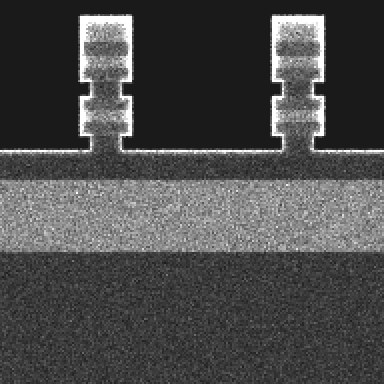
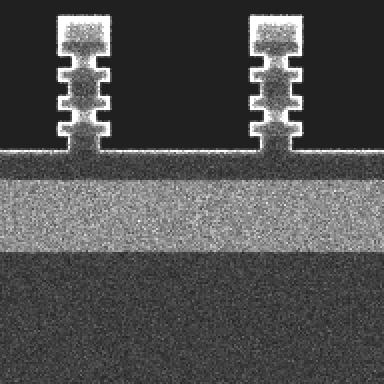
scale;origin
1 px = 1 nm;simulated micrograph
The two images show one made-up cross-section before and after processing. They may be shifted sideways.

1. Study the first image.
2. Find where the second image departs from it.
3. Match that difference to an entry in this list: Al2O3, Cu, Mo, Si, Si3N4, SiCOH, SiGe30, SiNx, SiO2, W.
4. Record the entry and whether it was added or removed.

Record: SiO2 / removed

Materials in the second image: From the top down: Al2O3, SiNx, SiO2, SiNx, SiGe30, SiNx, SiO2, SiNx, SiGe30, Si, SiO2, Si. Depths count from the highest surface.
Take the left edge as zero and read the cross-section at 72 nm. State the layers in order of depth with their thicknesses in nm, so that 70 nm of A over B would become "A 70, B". Al2O3 26, SiNx 14, SiO2 12, SiNx 14, SiGe30 14, SiNx 14, SiO2 12, SiNx 14, SiGe30 14, Si 30, SiO2 72, Si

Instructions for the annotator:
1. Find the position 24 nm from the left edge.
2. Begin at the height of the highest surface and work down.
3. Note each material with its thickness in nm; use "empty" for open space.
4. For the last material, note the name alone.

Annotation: empty 134, Si 30, SiO2 72, Si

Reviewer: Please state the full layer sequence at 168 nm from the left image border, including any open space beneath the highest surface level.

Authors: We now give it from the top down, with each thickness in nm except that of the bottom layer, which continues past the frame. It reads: empty 134, Si 30, SiO2 72, Si